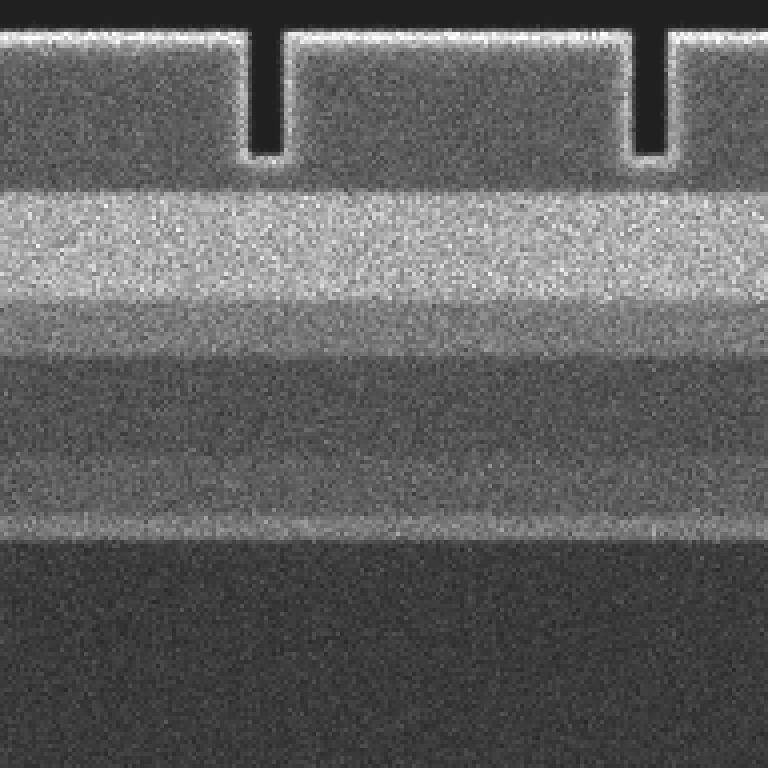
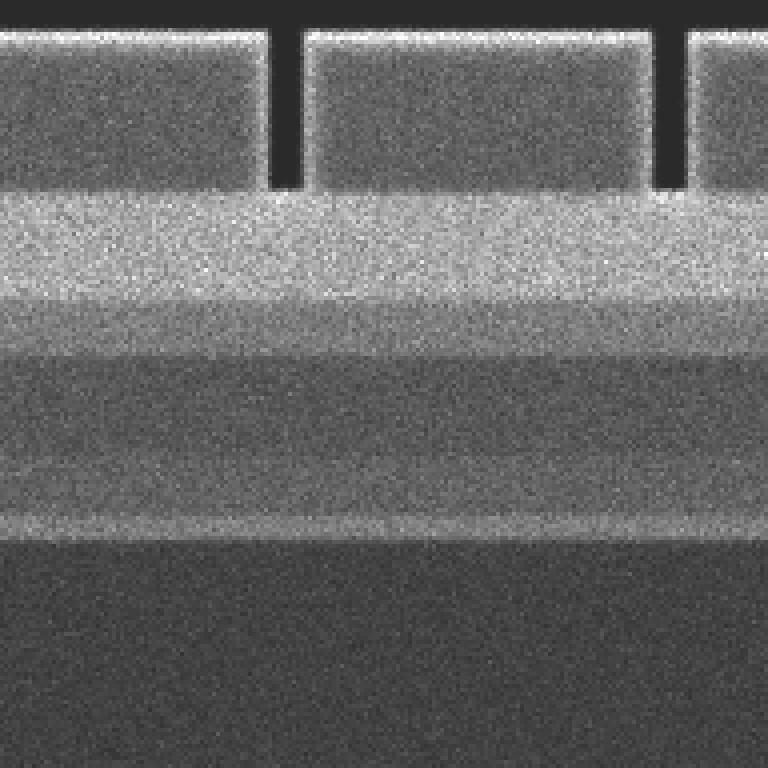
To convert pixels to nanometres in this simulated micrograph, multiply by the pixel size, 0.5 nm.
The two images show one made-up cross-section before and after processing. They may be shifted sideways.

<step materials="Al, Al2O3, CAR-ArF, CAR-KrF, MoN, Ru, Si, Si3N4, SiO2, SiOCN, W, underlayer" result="removed underlayer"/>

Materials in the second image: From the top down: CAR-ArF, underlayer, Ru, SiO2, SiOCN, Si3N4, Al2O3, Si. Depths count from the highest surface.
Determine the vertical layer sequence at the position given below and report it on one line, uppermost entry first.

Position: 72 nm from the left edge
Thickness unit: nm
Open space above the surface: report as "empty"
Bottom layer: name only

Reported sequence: CAR-ArF 62, underlayer 18, Ru 54, SiO2 28, SiOCN 50, Si3N4 30, Al2O3 12, Si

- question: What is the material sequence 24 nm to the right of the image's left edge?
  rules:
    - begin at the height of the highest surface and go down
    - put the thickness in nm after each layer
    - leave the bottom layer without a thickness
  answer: CAR-ArF 62, underlayer 18, Ru 54, SiO2 28, SiOCN 50, Si3N4 30, Al2O3 12, Si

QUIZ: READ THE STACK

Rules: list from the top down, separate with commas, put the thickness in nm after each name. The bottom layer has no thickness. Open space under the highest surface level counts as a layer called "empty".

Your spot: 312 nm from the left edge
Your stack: CAR-ArF 62, underlayer 18, Ru 54, SiO2 28, SiOCN 50, Si3N4 30, Al2O3 12, Si